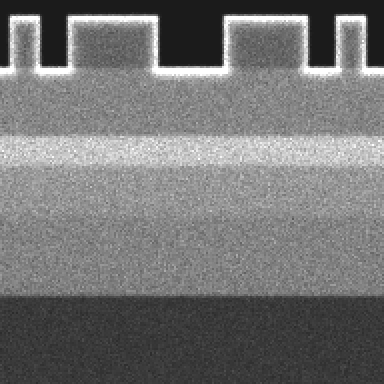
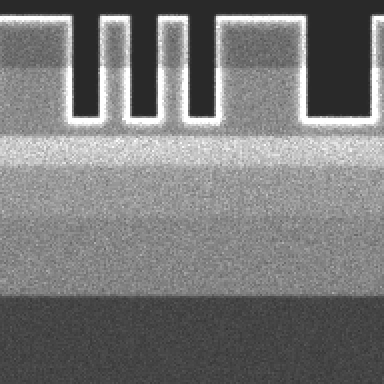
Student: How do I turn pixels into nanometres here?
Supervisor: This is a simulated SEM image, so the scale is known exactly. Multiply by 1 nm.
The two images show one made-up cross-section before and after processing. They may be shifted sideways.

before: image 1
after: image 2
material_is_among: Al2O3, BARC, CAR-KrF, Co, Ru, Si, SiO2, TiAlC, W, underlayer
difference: SiO2, removed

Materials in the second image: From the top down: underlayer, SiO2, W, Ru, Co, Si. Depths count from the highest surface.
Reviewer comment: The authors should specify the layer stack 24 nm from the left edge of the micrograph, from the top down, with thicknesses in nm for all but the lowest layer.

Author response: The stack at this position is underlayer 52, SiO2 68, W 30, Ru 50, Co 80, Si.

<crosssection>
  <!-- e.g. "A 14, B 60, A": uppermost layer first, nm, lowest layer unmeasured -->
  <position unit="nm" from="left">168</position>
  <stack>underlayer 52, SiO2 68, W 30, Ru 50, Co 80, Si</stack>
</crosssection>